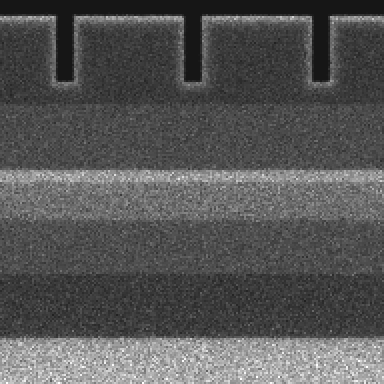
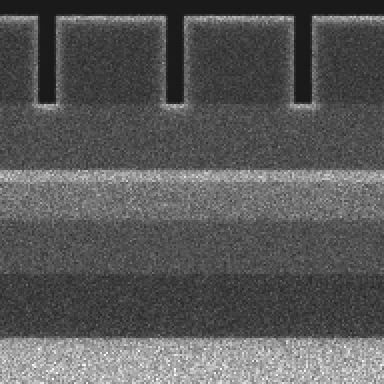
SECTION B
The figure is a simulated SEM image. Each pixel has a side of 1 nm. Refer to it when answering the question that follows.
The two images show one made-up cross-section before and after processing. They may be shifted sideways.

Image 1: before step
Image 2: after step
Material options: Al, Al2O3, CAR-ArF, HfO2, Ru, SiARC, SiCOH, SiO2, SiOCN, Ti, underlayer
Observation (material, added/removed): underlayer, removed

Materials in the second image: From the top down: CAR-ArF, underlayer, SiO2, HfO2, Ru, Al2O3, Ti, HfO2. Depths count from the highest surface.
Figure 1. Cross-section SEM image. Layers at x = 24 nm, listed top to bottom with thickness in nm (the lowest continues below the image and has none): CAR-ArF 66, underlayer 22, SiO2 66, HfO2 12, Ru 38, Al2O3 54, Ti 64, HfO2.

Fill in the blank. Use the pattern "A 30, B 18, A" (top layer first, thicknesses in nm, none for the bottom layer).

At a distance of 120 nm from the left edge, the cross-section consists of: CAR-ArF 66, underlayer 22, SiO2 66, HfO2 12, Ru 38, Al2O3 54, Ti 64, HfO2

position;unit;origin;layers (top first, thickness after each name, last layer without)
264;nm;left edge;CAR-ArF 66, underlayer 22, SiO2 66, HfO2 12, Ru 38, Al2O3 54, Ti 64, HfO2